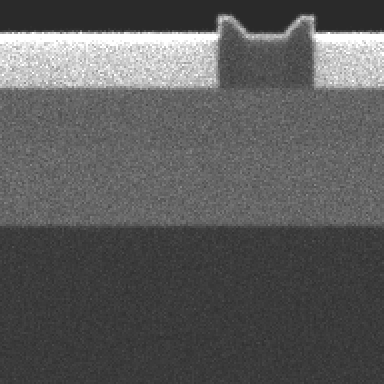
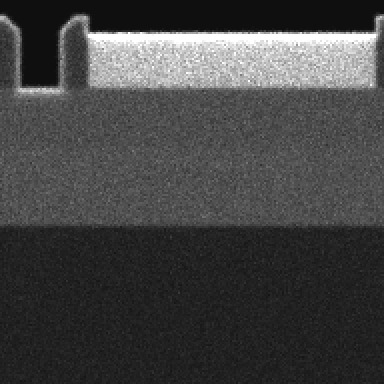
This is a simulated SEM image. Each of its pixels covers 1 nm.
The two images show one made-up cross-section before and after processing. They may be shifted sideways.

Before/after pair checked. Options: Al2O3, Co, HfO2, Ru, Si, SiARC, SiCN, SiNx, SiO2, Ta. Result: removed SiARC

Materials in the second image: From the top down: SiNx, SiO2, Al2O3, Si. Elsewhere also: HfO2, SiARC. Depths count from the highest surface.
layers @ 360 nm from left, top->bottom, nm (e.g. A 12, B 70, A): empty 18, HfO2 54, SiO2 58, Al2O3 80, Si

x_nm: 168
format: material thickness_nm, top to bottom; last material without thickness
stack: empty 18, HfO2 54, SiO2 58, Al2O3 80, Si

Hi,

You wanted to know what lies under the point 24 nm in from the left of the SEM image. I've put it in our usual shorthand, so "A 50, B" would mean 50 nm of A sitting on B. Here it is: empty 72, SiO2 58, Al2O3 80, Si